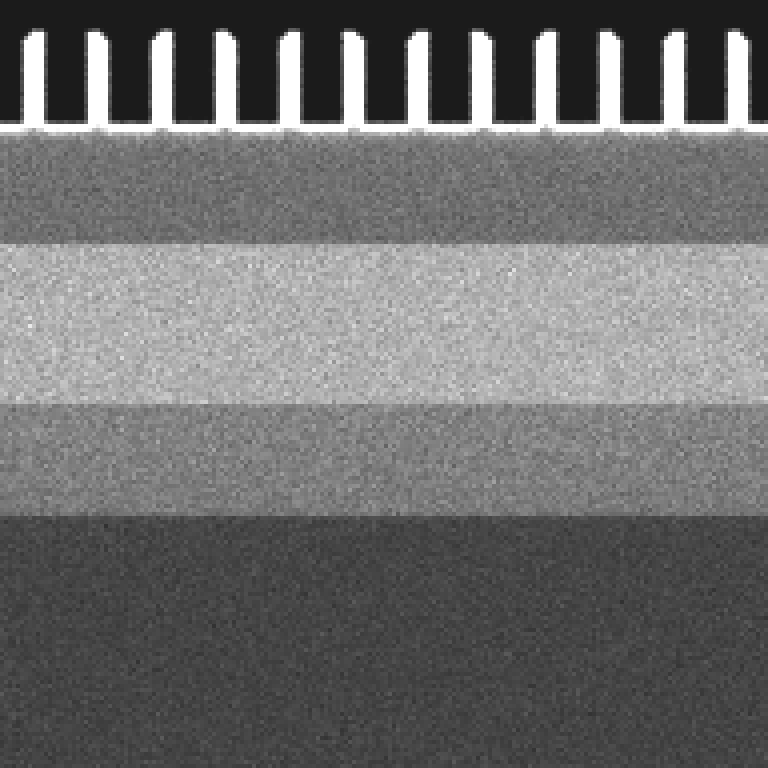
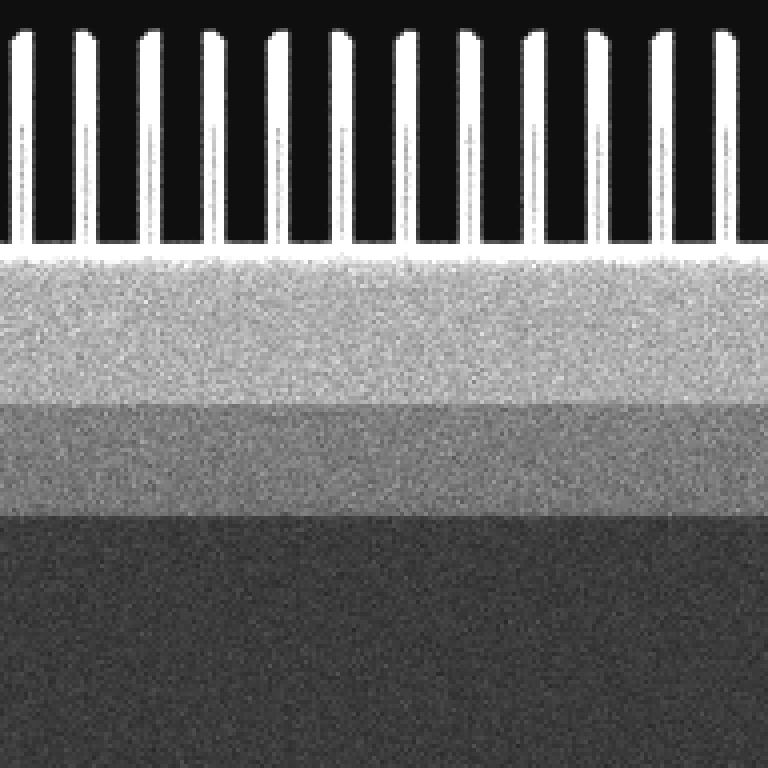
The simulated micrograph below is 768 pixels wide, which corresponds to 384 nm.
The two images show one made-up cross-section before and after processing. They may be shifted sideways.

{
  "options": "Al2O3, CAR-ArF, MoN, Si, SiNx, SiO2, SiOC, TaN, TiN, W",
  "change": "removed",
  "material": "SiNx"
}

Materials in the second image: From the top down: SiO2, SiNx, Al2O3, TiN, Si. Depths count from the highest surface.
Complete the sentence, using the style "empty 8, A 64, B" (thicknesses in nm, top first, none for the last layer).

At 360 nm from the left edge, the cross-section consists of SiO2 46, SiNx 60, Al2O3 80, TiN 56, Si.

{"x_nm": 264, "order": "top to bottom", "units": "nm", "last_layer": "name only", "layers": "empty 2, SiO2 44, SiNx 60, Al2O3 80, TiN 56, Si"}